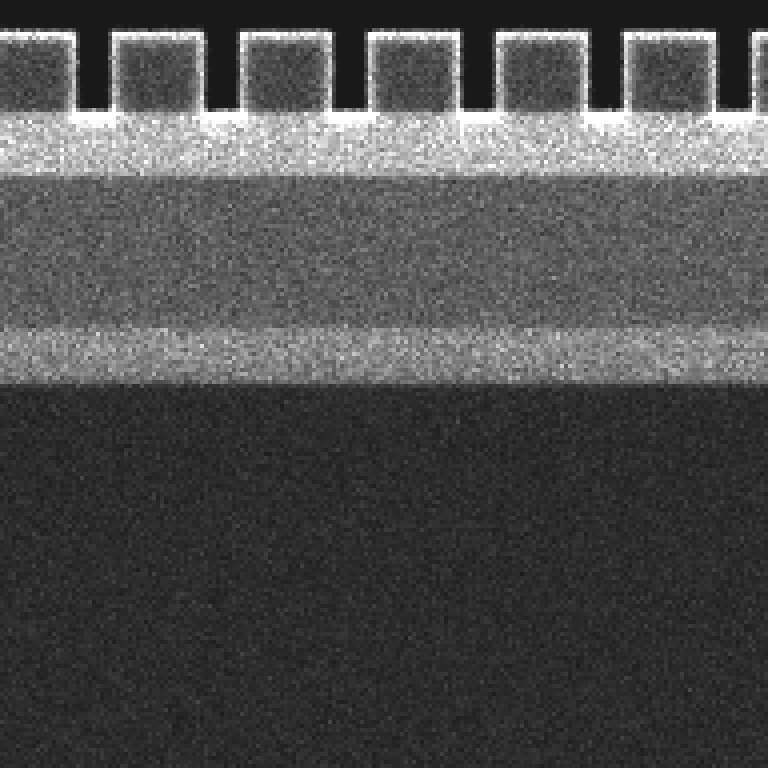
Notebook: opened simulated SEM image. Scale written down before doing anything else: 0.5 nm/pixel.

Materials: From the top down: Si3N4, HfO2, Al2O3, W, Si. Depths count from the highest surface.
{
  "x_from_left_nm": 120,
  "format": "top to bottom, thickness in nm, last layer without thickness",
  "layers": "Si3N4 40, HfO2 32, Al2O3 76, W 28, Si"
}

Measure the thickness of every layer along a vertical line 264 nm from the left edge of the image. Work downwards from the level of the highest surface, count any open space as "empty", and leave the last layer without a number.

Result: Si3N4 40, HfO2 32, Al2O3 76, W 28, Si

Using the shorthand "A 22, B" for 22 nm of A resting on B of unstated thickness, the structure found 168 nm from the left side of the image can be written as empty 40, HfO2 32, Al2O3 76, W 28, Si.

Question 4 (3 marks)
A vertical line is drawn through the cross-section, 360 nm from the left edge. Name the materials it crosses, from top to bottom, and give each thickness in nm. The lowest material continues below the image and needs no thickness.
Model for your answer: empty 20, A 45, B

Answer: empty 40, HfO2 32, Al2O3 76, W 28, Si